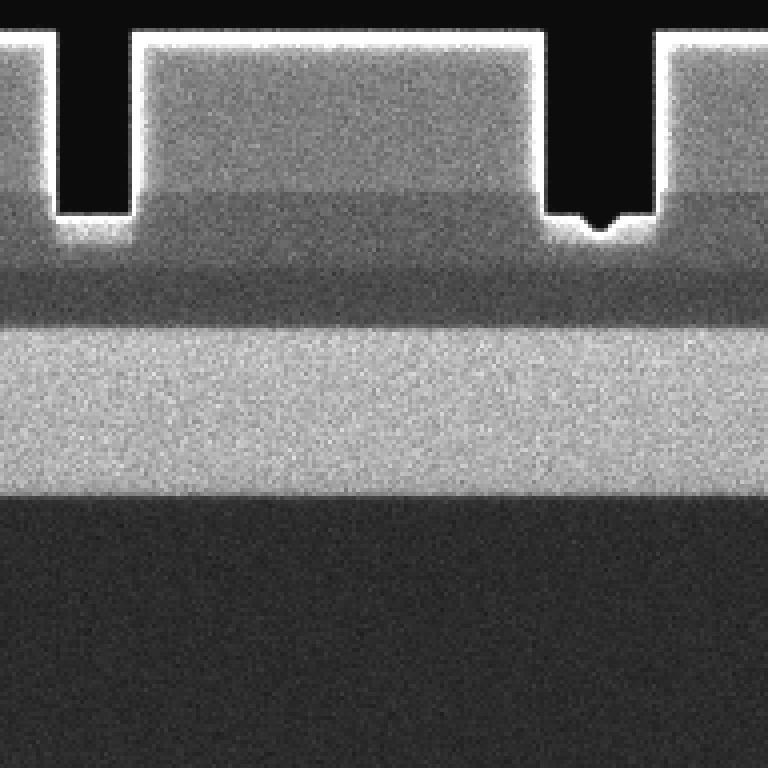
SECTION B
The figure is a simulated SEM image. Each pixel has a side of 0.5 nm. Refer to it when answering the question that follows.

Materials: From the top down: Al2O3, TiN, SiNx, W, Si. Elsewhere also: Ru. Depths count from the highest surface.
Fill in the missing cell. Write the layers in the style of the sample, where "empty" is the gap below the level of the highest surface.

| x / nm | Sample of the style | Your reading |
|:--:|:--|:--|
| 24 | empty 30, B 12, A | Al2O3 80, TiN 38, SiNx 30, W 84, Si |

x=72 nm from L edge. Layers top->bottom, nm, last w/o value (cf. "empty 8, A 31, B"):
Al2O3 80, TiN 38, SiNx 30, W 84, Si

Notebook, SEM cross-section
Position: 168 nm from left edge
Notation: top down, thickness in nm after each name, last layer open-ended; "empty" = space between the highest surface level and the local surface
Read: Al2O3 80, TiN 38, SiNx 30, W 84, Si